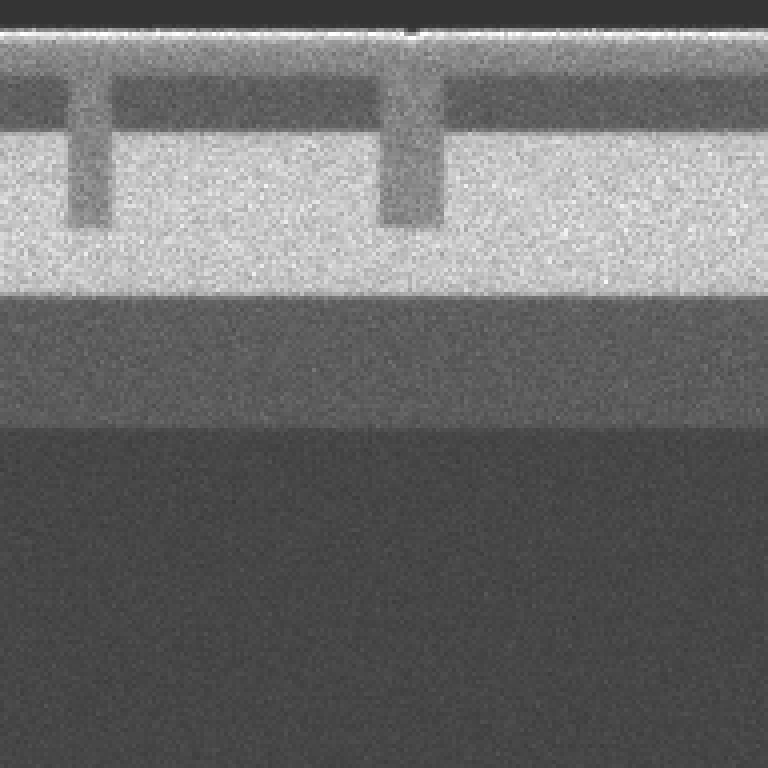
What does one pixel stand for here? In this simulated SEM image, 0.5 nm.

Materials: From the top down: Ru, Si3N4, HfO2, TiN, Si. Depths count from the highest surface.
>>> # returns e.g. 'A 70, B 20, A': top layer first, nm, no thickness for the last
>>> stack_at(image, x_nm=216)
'Ru 98, HfO2 34, TiN 66, Si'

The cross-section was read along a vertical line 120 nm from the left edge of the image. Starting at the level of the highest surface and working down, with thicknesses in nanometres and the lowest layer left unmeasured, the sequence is Ru 22, Si3N4 28, HfO2 82, TiN 66, Si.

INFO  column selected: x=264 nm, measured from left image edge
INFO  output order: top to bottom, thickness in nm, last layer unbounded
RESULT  Ru 22, Si3N4 28, HfO2 82, TiN 66, Si